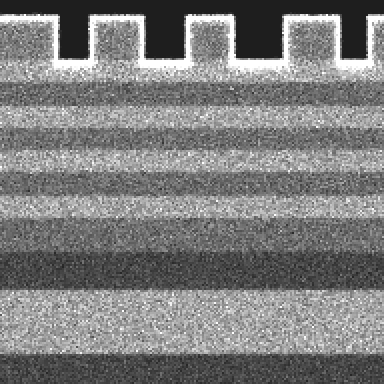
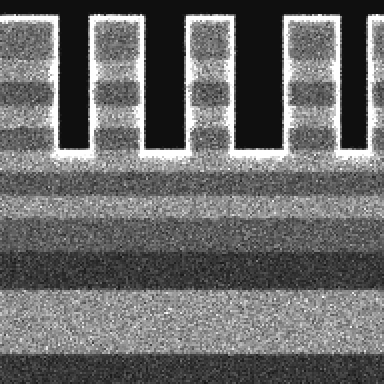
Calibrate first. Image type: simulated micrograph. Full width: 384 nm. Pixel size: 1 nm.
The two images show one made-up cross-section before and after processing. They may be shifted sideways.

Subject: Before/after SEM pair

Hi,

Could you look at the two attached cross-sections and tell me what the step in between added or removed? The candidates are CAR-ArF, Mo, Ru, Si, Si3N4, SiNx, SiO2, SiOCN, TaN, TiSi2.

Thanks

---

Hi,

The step removed SiNx and SiO2 and SiOCN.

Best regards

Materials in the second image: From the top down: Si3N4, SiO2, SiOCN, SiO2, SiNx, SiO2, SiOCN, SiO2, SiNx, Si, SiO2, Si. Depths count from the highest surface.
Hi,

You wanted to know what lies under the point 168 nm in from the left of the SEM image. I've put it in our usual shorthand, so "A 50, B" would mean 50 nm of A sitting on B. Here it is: empty 134, SiO2 22, SiOCN 24, SiO2 22, SiNx 34, Si 38, SiO2 64, Si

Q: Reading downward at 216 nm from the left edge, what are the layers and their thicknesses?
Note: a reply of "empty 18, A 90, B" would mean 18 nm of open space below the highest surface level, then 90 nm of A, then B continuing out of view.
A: Si3N4 44, SiO2 22, SiOCN 24, SiO2 22, SiNx 22, SiO2 22, SiOCN 24, SiO2 22, SiNx 34, Si 38, SiO2 64, Si